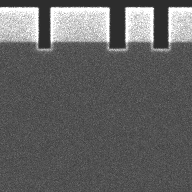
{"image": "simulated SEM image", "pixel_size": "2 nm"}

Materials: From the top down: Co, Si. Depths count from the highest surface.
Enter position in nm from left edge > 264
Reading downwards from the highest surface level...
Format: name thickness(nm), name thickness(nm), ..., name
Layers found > Co 68, Si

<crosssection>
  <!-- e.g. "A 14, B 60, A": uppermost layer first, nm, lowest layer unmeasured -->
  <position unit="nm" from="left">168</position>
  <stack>Co 68, Si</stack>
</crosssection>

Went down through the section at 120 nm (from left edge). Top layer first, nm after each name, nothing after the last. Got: Co 68, Si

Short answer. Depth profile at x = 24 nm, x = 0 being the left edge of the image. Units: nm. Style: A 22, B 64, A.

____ Co 68, Si